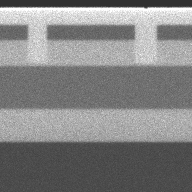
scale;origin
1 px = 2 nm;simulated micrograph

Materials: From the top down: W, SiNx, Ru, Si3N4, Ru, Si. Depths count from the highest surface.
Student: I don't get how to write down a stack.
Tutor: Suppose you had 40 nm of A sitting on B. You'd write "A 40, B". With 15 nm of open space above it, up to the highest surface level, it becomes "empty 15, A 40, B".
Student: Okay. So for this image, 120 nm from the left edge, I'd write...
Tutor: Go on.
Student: W 34, SiNx 30, Ru 52, Si3N4 86, Ru 66, Si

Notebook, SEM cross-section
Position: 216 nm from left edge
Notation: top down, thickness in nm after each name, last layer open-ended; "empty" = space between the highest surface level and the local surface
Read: W 34, SiNx 30, Ru 52, Si3N4 86, Ru 66, Si